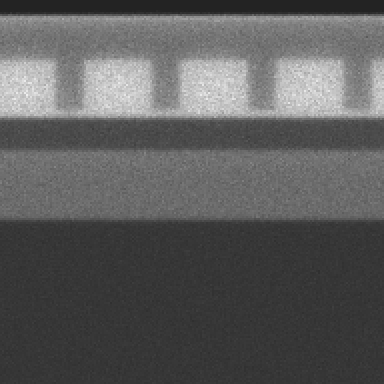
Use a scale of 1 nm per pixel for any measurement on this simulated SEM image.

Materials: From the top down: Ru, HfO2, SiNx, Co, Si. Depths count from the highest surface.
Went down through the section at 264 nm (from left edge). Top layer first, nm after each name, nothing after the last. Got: Ru 94, HfO2 8, SiNx 32, Co 70, Si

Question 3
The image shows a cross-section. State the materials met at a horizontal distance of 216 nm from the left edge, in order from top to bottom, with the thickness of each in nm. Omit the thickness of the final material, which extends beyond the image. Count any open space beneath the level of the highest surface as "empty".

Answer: Ru 44, HfO2 58, SiNx 32, Co 70, Si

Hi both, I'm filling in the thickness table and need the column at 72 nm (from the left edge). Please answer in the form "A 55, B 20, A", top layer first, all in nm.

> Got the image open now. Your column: Ru 94, HfO2 8, SiNx 32, Co 70, Si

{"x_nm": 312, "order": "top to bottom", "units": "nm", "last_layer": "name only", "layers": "Ru 44, HfO2 58, SiNx 32, Co 70, Si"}